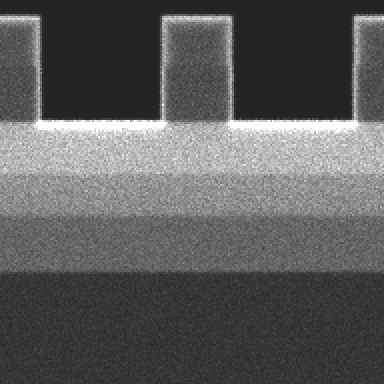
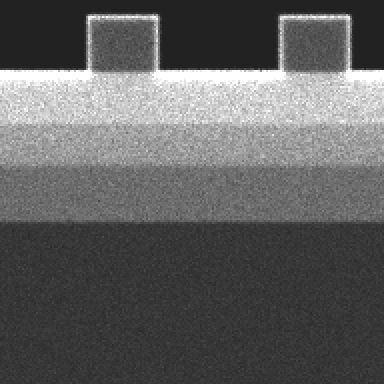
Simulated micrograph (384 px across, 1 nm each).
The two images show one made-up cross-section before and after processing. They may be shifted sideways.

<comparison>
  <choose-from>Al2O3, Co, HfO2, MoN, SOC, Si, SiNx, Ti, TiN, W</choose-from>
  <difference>SOC removed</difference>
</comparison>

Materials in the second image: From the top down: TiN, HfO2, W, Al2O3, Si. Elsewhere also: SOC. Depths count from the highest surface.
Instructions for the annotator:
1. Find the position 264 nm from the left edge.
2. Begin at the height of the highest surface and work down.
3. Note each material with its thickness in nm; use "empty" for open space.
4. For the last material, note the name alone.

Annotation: empty 56, HfO2 52, W 42, Al2O3 56, Si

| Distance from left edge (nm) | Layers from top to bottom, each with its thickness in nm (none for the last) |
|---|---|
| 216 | empty 56, HfO2 52, W 42, Al2O3 56, Si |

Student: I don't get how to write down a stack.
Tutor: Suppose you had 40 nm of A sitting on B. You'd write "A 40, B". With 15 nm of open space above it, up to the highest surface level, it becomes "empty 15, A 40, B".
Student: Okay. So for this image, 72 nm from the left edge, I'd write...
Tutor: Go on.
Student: empty 56, HfO2 52, W 42, Al2O3 56, Si